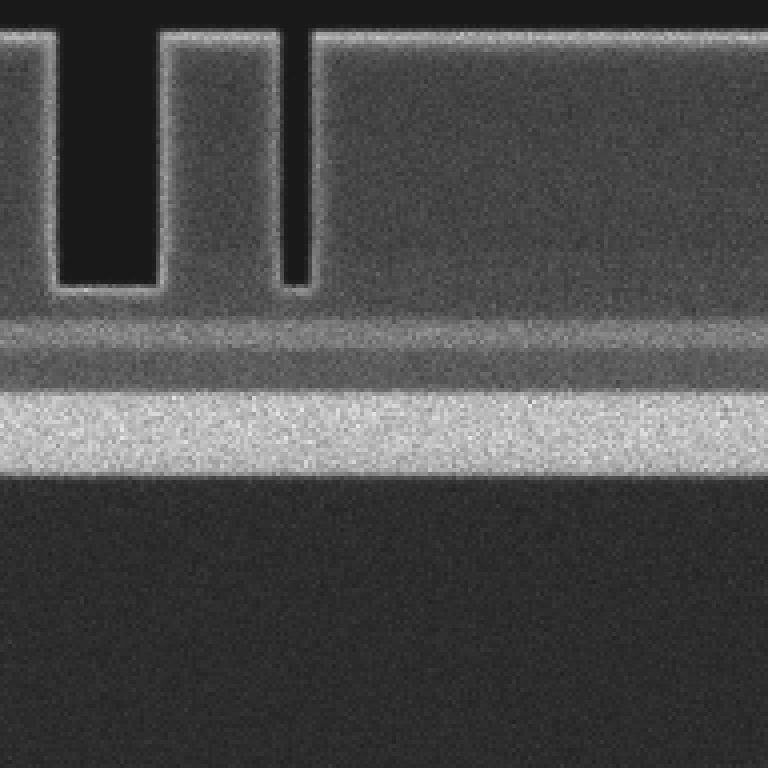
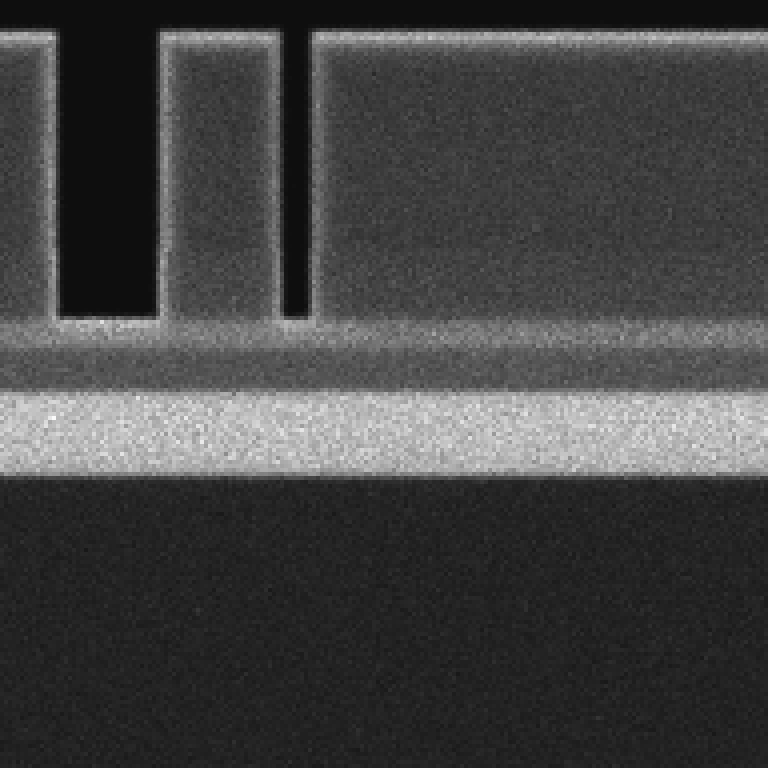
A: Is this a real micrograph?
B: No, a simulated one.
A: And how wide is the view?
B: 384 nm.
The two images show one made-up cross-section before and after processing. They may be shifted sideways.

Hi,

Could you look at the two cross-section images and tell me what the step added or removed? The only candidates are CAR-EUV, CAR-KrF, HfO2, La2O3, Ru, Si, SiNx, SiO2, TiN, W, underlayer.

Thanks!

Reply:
removed TiN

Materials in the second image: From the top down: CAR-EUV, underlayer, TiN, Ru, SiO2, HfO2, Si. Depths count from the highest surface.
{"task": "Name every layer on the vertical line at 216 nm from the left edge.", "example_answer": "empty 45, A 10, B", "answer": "CAR-EUV 54, underlayer 56, TiN 34, Ru 14, SiO2 22, HfO2 42, Si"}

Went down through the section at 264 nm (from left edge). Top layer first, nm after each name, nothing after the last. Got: CAR-EUV 54, underlayer 56, TiN 34, Ru 14, SiO2 22, HfO2 42, Si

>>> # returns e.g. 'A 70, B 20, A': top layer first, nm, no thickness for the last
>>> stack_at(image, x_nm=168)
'CAR-EUV 54, underlayer 56, TiN 34, Ru 14, SiO2 22, HfO2 42, Si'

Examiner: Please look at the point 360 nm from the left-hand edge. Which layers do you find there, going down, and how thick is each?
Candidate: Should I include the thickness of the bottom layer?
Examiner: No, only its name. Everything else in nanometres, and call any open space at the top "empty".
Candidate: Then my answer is CAR-EUV 54, underlayer 56, TiN 34, Ru 14, SiO2 22, HfO2 42, Si